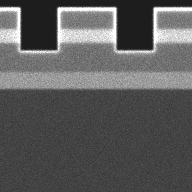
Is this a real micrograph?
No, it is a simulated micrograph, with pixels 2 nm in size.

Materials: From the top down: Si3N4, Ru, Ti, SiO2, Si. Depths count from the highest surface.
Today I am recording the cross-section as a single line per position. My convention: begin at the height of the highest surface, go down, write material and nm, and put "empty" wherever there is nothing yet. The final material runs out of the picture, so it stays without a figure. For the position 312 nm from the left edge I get Si3N4 42, Ru 28, Ti 58, SiO2 34, Si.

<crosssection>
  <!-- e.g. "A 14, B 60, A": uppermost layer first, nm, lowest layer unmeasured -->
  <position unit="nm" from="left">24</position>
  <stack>Si3N4 42, Ru 28, Ti 58, SiO2 34, Si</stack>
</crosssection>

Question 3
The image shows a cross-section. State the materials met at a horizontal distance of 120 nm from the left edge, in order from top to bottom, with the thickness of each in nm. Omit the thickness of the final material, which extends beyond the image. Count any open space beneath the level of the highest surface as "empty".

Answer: Si3N4 42, Ru 28, Ti 58, SiO2 34, Si